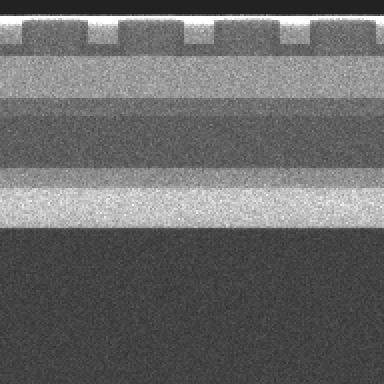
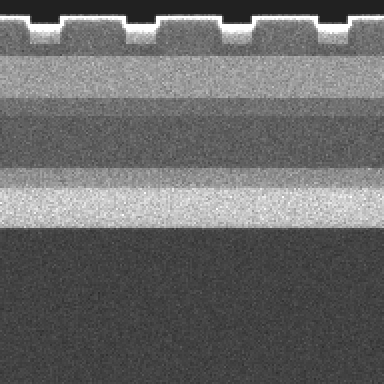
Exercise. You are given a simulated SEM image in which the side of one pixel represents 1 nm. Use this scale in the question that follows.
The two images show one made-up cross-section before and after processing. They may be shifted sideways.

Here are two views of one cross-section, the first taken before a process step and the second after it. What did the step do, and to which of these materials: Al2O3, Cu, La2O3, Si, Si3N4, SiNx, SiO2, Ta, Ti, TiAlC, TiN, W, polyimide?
It removed SiO2.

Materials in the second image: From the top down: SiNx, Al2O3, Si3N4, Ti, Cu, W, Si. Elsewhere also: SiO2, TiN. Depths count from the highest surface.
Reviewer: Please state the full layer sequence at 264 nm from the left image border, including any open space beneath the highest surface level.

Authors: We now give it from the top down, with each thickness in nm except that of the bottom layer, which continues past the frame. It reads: TiN 40, Al2O3 42, Si3N4 18, Ti 52, Cu 20, W 40, Si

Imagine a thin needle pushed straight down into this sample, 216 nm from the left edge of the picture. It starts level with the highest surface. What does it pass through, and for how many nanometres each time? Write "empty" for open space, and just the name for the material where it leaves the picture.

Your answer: SiNx 40, Al2O3 42, Si3N4 18, Ti 52, Cu 20, W 40, Si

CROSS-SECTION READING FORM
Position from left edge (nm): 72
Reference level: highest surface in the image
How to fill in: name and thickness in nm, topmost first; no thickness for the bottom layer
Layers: TiN 40, Al2O3 42, Si3N4 18, Ti 52, Cu 20, W 40, Si